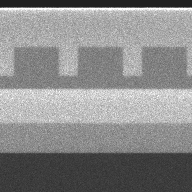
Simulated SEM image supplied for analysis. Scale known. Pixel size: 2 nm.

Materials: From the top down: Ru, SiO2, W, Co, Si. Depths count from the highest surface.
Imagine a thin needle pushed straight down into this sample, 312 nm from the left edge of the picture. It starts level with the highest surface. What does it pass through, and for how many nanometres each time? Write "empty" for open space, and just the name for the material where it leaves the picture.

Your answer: Ru 78, SiO2 84, W 68, Co 60, Si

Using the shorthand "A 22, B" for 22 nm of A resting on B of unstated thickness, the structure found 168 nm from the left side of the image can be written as Ru 78, SiO2 84, W 68, Co 60, Si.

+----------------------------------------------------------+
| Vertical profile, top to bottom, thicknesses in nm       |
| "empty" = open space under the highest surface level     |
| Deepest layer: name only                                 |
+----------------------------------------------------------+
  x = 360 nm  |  Ru 78, SiO2 84, W 68, Co 60, Si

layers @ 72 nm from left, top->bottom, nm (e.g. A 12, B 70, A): Ru 78, SiO2 84, W 68, Co 60, Si